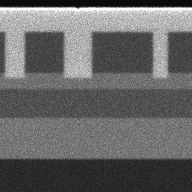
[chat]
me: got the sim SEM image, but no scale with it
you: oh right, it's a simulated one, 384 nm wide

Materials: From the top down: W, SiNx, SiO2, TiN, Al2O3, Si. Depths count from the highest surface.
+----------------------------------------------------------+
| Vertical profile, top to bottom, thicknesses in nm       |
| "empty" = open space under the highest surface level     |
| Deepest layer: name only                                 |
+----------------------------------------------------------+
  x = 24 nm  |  W 140, SiO2 22, TiN 58, Al2O3 82, Si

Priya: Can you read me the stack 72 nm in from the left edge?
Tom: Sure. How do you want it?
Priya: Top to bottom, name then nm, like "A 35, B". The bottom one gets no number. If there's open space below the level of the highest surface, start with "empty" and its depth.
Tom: W 48, SiNx 82, SiO2 32, TiN 58, Al2O3 82, Si